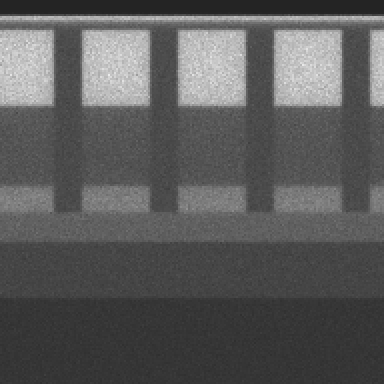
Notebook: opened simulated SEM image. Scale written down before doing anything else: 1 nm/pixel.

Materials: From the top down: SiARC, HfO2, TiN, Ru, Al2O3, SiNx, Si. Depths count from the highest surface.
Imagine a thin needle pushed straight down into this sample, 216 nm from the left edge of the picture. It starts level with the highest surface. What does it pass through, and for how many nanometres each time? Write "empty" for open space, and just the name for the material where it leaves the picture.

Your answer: SiARC 14, HfO2 76, TiN 80, Ru 26, Al2O3 30, SiNx 56, Si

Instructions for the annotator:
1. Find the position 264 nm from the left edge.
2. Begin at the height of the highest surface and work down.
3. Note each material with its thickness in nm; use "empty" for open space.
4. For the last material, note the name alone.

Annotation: SiARC 196, Al2O3 30, SiNx 56, Si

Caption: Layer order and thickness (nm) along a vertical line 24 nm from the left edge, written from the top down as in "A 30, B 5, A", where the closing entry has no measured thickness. SiARC 14, HfO2 76, TiN 80, Ru 26, Al2O3 30, SiNx 56, Si